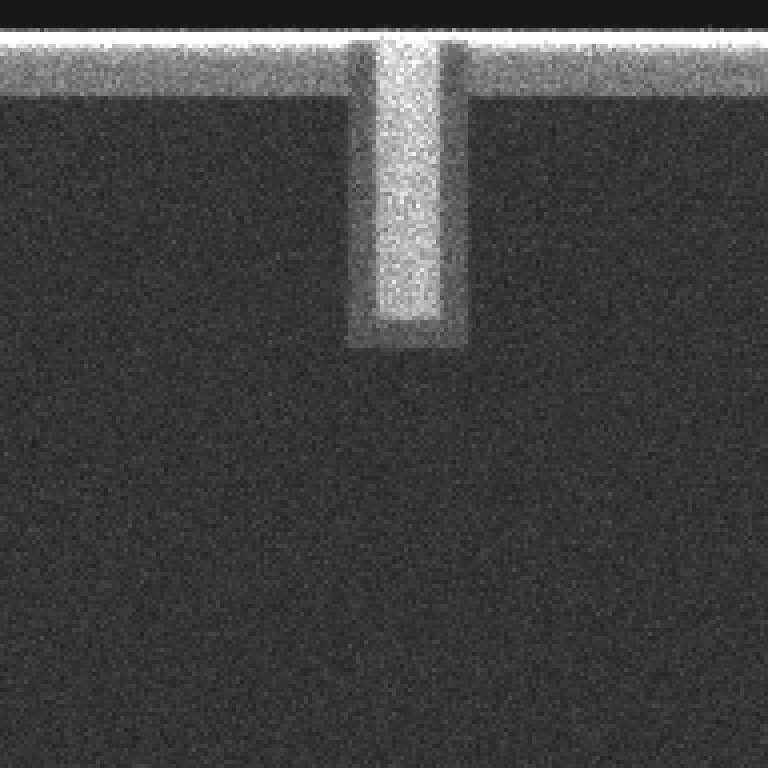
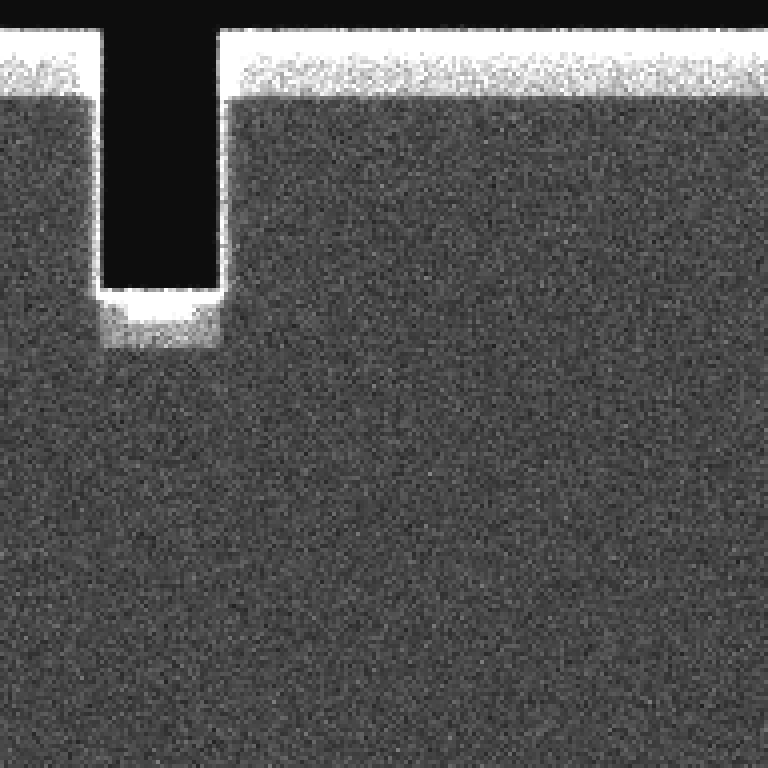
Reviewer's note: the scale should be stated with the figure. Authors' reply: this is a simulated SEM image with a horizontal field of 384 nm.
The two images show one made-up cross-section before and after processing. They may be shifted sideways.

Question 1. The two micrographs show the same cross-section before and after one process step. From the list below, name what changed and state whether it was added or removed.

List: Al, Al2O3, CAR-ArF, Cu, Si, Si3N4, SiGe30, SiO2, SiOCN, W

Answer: Si3N4 and W, removed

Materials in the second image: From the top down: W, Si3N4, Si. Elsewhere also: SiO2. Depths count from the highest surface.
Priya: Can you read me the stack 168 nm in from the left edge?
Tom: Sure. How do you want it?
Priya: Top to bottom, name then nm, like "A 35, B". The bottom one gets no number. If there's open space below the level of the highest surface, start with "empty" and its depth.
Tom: SiO2 32, Si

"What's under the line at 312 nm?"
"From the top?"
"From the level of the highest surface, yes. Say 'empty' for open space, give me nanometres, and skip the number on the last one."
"SiO2 32, Si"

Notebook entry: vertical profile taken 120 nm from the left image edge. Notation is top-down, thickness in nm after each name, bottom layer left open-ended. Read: SiO2 32, Si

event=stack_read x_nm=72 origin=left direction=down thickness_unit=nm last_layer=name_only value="empty 130, W 14, Si3N4 14, Si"